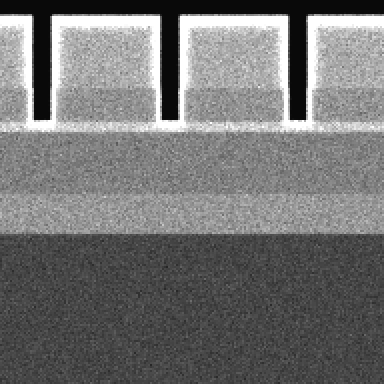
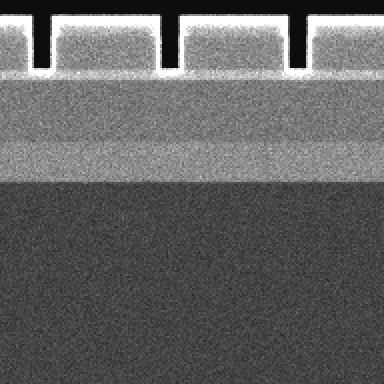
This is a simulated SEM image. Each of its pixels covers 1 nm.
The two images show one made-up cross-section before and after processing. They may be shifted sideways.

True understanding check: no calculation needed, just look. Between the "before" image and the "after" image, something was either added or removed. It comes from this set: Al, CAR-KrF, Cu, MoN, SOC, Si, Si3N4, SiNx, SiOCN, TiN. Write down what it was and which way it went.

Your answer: SOC (removed)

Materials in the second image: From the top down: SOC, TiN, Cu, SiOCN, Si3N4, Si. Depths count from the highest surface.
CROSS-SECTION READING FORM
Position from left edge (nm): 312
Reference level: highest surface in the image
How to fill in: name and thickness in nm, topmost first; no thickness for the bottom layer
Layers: SOC 20, TiN 34, Cu 10, SiOCN 62, Si3N4 40, Si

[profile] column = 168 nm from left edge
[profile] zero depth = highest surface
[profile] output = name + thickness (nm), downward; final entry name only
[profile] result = empty 54, Cu 10, SiOCN 62, Si3N4 40, Si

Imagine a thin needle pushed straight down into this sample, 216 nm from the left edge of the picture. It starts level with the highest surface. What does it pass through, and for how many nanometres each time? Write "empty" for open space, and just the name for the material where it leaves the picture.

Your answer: SOC 20, TiN 34, Cu 10, SiOCN 62, Si3N4 40, Si